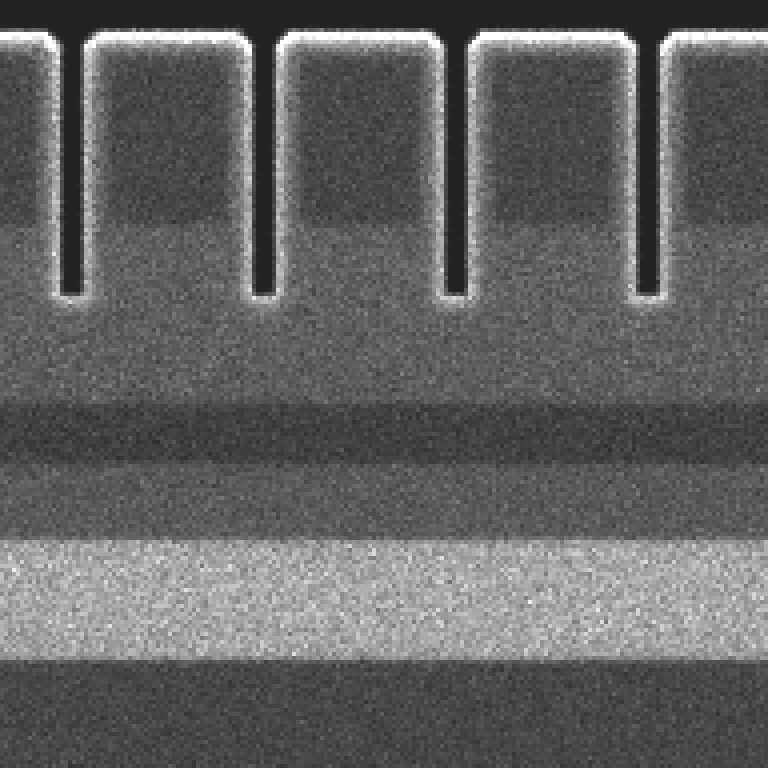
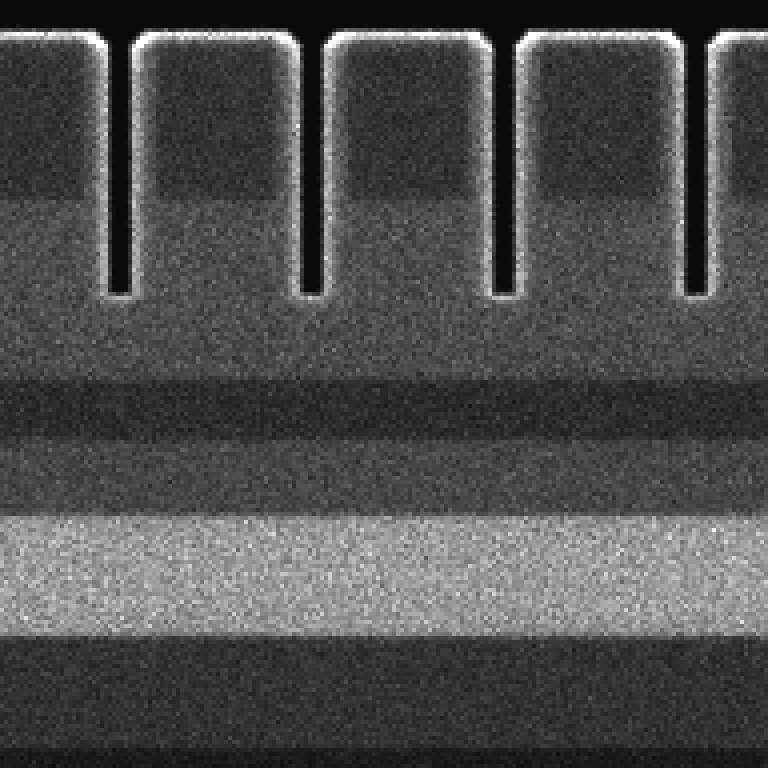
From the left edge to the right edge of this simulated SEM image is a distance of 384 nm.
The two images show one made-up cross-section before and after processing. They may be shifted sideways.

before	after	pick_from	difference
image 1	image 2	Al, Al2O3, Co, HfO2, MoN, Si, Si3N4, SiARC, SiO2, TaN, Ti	Al2O3 removed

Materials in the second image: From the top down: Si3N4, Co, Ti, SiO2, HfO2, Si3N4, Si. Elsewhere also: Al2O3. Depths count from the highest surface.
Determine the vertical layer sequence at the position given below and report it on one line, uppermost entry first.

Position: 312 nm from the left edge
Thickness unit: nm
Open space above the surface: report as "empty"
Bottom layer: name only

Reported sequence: Si3N4 84, Co 90, Ti 30, SiO2 38, HfO2 60, Si3N4 56, Si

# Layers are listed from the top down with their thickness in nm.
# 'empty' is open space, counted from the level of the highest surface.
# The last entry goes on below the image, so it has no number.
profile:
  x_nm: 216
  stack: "Si3N4 84, Co 90, Ti 30, SiO2 38, HfO2 60, Si3N4 56, Si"